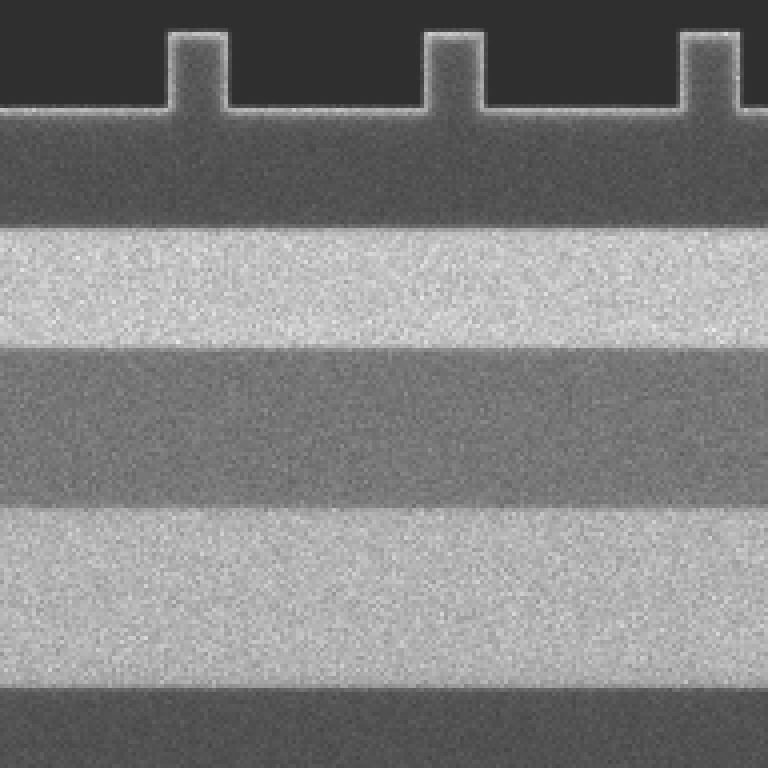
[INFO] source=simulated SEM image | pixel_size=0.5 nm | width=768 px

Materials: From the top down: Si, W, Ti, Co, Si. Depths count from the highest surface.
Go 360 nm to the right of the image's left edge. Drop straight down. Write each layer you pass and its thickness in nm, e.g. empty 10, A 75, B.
Si 98, W 60, Ti 80, Co 90, Si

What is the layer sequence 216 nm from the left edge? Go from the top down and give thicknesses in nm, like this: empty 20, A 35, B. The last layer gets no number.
Si 98, W 60, Ti 80, Co 90, Si